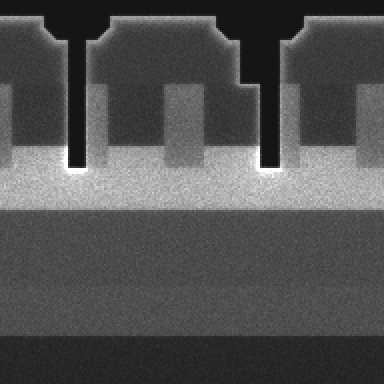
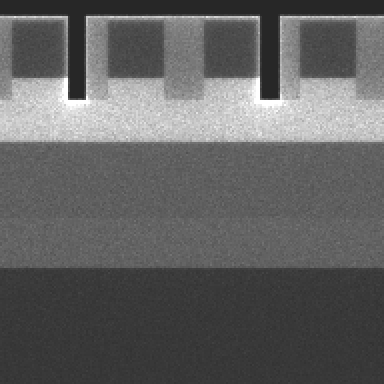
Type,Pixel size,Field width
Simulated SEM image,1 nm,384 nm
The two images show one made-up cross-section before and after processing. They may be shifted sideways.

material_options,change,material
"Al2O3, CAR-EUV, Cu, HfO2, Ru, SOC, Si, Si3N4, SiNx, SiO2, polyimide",removed,SOC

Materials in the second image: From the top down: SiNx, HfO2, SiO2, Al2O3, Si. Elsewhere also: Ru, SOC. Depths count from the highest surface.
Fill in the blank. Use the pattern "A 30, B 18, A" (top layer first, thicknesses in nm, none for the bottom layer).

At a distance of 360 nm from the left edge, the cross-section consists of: Ru 84, HfO2 42, SiO2 76, Al2O3 50, Si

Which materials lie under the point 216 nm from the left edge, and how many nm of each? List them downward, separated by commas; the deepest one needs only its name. SiNx 62, HfO2 64, SiO2 76, Al2O3 50, Si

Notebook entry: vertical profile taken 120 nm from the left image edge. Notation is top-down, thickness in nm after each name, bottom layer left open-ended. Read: SiNx 62, HfO2 64, SiO2 76, Al2O3 50, Si